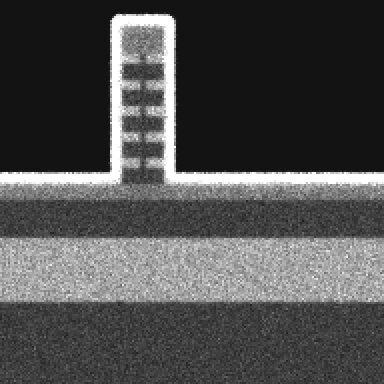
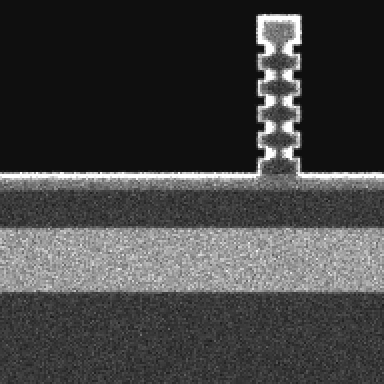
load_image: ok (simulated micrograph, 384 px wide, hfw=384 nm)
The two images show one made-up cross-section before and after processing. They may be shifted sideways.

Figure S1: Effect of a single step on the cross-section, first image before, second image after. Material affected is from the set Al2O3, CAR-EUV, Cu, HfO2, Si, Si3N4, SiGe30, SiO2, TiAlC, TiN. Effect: removed Al2O3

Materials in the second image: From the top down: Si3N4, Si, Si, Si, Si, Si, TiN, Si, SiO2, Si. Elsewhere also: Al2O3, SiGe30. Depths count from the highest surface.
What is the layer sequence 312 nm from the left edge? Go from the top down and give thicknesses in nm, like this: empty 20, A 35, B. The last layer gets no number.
empty 158, TiN 16, Si 38, SiO2 64, Si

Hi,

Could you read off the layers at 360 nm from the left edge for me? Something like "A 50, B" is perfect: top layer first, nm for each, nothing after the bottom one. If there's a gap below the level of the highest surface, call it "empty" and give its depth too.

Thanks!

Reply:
empty 158, TiN 16, Si 38, SiO2 64, Si